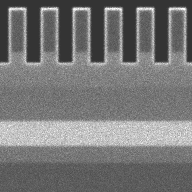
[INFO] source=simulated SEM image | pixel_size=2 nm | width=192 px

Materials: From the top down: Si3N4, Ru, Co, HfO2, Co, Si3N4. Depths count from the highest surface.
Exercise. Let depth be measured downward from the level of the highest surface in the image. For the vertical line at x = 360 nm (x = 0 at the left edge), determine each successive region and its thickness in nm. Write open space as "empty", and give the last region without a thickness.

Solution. Si3N4 88, Ru 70, Co 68, HfO2 50, Co 34, Si3N4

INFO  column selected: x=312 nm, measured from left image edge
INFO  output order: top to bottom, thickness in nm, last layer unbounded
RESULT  empty 110, Ru 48, Co 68, HfO2 50, Co 34, Si3N4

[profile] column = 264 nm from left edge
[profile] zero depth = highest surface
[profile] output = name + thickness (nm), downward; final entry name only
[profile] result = empty 110, Ru 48, Co 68, HfO2 50, Co 34, Si3N4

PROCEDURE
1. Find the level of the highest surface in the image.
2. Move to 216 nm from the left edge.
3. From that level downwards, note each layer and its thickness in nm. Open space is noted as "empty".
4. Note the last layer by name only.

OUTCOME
Si3N4 88, Ru 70, Co 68, HfO2 50, Co 34, Si3N4